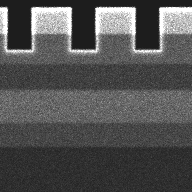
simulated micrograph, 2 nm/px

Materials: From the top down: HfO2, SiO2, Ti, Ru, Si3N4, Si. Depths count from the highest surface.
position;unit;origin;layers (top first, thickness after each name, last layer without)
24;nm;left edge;empty 84, SiO2 28, Ti 52, Ru 66, Si3N4 48, Si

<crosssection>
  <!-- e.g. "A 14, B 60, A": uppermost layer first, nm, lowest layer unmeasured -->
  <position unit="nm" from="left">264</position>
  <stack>HfO2 52, SiO2 60, Ti 52, Ru 66, Si3N4 48, Si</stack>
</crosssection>